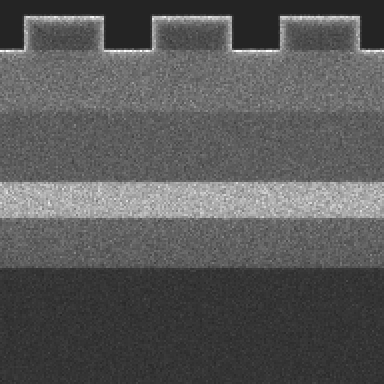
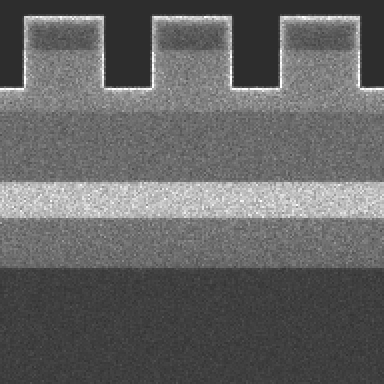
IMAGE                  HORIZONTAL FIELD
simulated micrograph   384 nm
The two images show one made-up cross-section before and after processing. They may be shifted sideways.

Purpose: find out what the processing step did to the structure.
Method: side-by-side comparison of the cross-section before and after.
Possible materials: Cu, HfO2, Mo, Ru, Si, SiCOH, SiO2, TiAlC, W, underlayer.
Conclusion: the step removed Ru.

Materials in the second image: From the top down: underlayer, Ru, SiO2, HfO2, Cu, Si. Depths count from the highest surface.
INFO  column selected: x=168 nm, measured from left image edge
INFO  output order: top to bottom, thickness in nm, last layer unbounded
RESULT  underlayer 34, Ru 62, SiO2 70, HfO2 36, Cu 50, Si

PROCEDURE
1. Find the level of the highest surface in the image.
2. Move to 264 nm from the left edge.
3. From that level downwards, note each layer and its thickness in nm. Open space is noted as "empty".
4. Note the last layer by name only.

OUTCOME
empty 72, Ru 24, SiO2 70, HfO2 36, Cu 50, Si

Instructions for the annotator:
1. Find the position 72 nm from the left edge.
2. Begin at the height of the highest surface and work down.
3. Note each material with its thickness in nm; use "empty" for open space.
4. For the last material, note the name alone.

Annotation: underlayer 34, Ru 62, SiO2 70, HfO2 36, Cu 50, Si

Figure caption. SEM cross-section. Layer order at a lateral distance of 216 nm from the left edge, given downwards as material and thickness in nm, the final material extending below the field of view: underlayer 34, Ru 62, SiO2 70, HfO2 36, Cu 50, Si